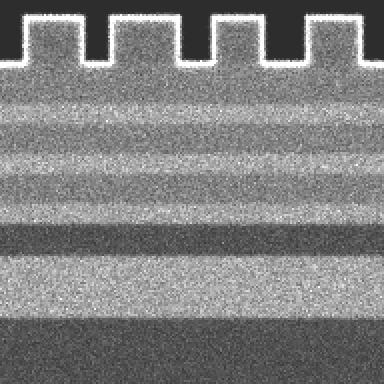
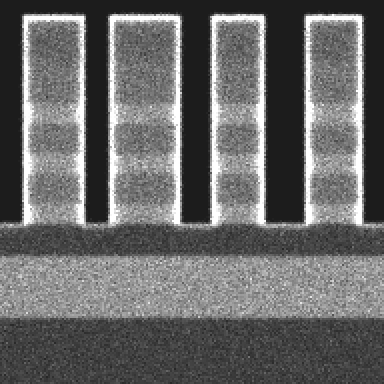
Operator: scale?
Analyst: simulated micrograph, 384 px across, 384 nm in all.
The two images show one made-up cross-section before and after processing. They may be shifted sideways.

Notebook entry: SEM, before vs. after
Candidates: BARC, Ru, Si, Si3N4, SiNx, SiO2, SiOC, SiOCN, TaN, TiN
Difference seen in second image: Si3N4 and SiO2 removed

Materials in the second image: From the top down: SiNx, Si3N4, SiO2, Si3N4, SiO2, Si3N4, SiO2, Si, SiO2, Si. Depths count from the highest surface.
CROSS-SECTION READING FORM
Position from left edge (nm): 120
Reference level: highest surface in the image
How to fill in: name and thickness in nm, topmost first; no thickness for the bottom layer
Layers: SiNx 46, Si3N4 42, SiO2 20, Si3N4 30, SiO2 20, Si3N4 30, SiO2 20, Si 32, SiO2 62, Si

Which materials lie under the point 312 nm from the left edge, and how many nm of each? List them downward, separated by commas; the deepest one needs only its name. SiNx 46, Si3N4 42, SiO2 20, Si3N4 30, SiO2 20, Si3N4 30, SiO2 20, Si 32, SiO2 62, Si